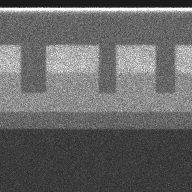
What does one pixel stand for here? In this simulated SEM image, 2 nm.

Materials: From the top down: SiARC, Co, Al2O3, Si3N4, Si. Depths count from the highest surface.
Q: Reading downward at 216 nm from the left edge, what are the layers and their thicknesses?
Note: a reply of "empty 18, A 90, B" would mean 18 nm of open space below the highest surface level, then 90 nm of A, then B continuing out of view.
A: SiARC 170, Al2O3 38, Si3N4 34, Si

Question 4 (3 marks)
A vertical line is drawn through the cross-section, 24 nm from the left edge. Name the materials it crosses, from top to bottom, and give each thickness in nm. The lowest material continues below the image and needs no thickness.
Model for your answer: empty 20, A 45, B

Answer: SiARC 74, Co 56, Al2O3 78, Si3N4 34, Si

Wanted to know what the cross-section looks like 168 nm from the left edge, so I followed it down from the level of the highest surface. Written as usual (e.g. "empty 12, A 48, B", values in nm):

SiARC 74, Co 56, Al2O3 78, Si3N4 34, Si